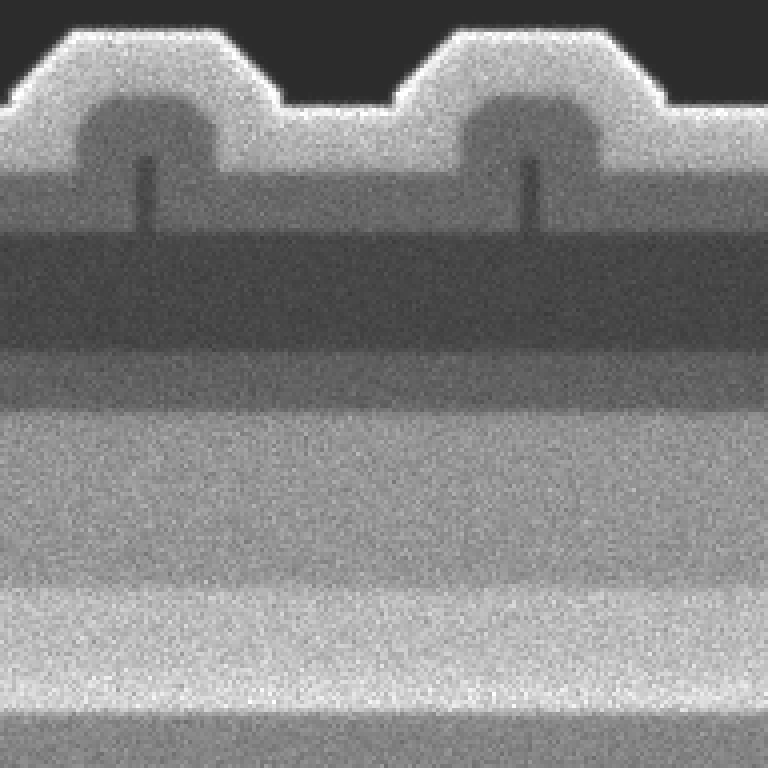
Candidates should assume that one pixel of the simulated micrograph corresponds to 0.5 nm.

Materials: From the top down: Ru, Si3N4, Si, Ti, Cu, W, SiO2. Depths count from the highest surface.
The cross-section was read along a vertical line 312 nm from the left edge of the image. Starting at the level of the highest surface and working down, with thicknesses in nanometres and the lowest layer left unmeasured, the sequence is empty 12, Ru 58, Si3N4 30, Si 60, Ti 30, Cu 88, W 62, SiO2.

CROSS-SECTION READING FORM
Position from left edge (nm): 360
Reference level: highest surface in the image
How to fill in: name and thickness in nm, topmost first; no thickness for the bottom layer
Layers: empty 38, Ru 32, Si3N4 30, Si 60, Ti 30, Cu 88, W 62, SiO2